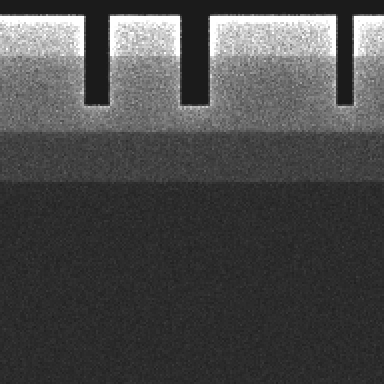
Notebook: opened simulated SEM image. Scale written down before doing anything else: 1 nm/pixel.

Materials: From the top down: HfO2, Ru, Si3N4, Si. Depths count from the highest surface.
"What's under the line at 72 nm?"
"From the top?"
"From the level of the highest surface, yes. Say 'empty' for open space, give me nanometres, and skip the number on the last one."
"HfO2 40, Ru 76, Si3N4 50, Si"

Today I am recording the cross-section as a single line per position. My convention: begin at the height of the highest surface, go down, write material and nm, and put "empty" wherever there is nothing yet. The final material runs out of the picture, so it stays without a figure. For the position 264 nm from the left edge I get HfO2 40, Ru 76, Si3N4 50, Si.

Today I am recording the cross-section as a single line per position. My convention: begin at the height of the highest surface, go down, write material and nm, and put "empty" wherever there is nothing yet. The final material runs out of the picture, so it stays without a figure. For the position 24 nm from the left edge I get HfO2 40, Ru 76, Si3N4 50, Si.